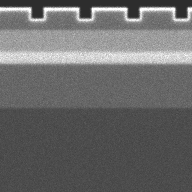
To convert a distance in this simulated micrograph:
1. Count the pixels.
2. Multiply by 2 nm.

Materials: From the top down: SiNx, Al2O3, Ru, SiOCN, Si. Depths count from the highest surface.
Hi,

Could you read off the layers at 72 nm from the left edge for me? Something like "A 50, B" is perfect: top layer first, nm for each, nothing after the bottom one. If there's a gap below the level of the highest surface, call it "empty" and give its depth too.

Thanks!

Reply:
empty 22, SiNx 22, Al2O3 44, Ru 24, SiOCN 88, Si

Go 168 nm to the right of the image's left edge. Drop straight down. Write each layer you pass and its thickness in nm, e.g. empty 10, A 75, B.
empty 22, SiNx 22, Al2O3 44, Ru 24, SiOCN 88, Si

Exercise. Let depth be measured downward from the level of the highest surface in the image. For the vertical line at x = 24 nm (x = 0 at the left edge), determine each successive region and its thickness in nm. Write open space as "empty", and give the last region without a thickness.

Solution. SiNx 44, Al2O3 44, Ru 24, SiOCN 88, Si